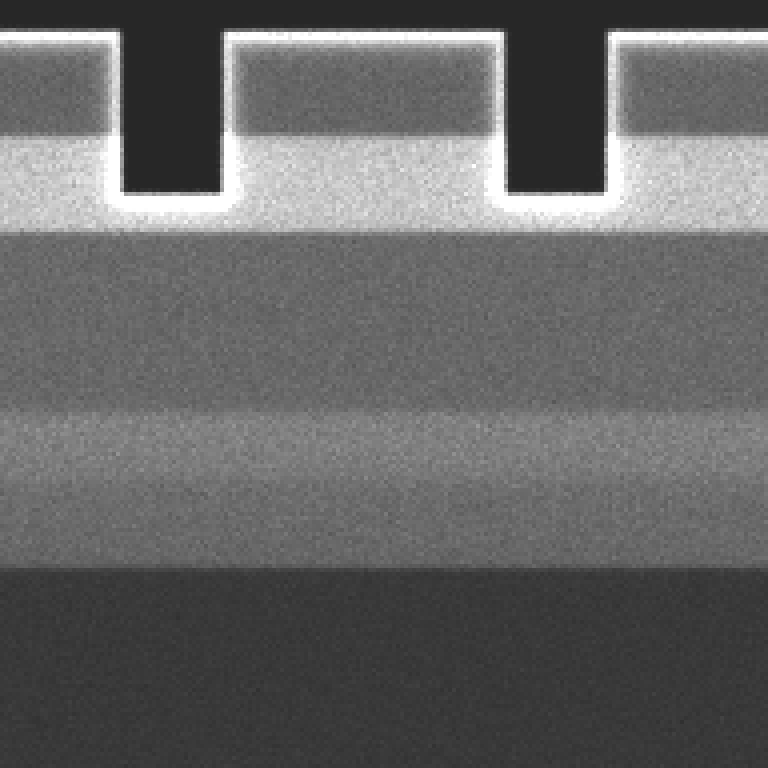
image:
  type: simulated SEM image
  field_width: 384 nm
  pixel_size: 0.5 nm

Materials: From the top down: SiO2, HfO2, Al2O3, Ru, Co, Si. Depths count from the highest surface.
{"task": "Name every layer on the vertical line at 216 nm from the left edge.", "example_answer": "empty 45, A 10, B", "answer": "SiO2 52, HfO2 48, Al2O3 90, Ru 34, Co 44, Si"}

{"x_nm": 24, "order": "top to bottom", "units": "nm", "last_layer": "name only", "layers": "SiO2 52, HfO2 48, Al2O3 90, Ru 34, Co 44, Si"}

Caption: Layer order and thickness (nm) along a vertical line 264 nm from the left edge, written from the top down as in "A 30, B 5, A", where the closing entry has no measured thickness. empty 82, HfO2 18, Al2O3 90, Ru 34, Co 44, Si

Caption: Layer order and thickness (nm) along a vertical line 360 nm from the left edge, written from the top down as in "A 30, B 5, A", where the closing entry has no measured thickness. SiO2 52, HfO2 48, Al2O3 90, Ru 34, Co 44, Si